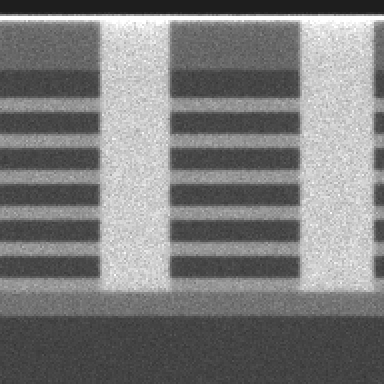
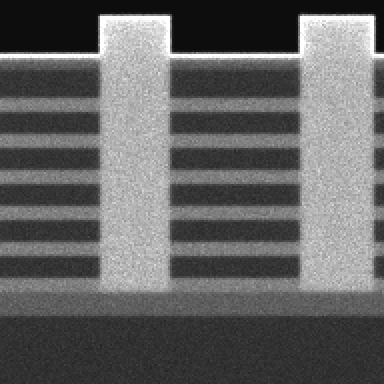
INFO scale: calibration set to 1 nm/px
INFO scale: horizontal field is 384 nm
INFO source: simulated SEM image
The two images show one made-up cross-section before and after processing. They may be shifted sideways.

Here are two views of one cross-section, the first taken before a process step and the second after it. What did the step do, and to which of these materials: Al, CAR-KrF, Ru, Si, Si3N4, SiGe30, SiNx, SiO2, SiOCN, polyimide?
It removed SiNx.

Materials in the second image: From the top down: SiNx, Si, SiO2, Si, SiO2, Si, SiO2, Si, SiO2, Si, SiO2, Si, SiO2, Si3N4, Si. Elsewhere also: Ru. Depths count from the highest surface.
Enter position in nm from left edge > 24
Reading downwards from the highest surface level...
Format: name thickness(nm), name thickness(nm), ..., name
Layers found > empty 38, SiNx 16, Si 28, SiO2 14, Si 22, SiO2 14, Si 22, SiO2 14, Si 22, SiO2 14, Si 22, SiO2 14, Si 22, SiO2 14, Si3N4 24, Si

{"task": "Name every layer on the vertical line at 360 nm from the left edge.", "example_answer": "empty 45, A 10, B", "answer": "Ru 276, Si3N4 24, Si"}